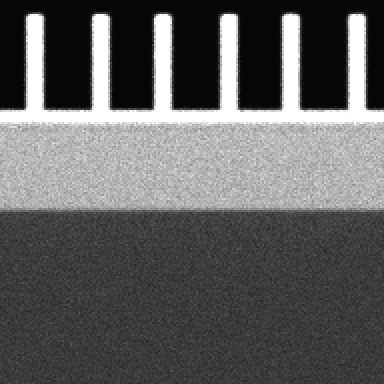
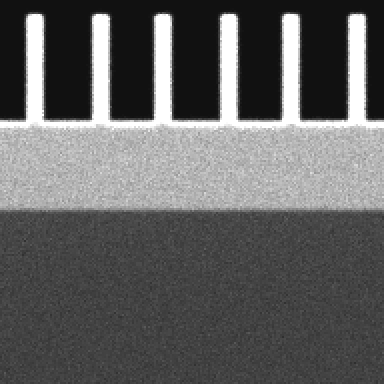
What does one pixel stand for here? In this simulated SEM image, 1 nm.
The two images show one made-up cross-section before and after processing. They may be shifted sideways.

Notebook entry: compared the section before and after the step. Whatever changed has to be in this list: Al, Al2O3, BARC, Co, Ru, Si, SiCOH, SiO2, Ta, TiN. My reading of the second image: Co removed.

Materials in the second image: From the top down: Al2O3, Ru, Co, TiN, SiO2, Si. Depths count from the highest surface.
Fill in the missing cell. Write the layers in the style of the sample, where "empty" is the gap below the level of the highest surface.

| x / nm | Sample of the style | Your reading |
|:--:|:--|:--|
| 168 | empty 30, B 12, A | Al2O3 40, Ru 56, Co 10, TiN 10, SiO2 78, Si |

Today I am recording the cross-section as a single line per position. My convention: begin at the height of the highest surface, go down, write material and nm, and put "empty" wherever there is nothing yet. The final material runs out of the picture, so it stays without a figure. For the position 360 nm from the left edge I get Al2O3 40, Ru 56, Co 10, TiN 10, SiO2 78, Si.